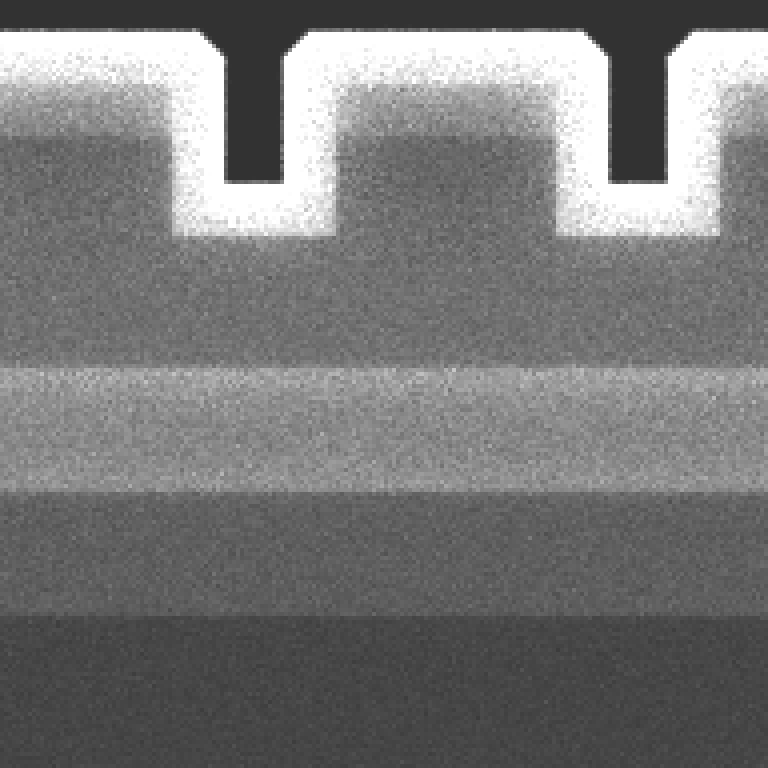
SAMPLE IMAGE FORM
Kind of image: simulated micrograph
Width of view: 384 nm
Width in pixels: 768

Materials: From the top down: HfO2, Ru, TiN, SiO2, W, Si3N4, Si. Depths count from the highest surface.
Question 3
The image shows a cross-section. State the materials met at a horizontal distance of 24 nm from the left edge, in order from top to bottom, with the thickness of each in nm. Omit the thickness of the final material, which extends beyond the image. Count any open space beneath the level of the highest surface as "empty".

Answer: HfO2 26, Ru 26, TiN 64, SiO2 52, W 62, Si3N4 62, Si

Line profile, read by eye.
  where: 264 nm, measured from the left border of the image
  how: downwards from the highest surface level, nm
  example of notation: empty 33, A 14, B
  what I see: HfO2 26, Ru 26, TiN 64, SiO2 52, W 62, Si3N4 62, Si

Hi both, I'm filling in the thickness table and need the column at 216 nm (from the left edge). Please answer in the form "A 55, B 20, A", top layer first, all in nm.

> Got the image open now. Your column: HfO2 26, Ru 26, TiN 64, SiO2 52, W 62, Si3N4 62, Si